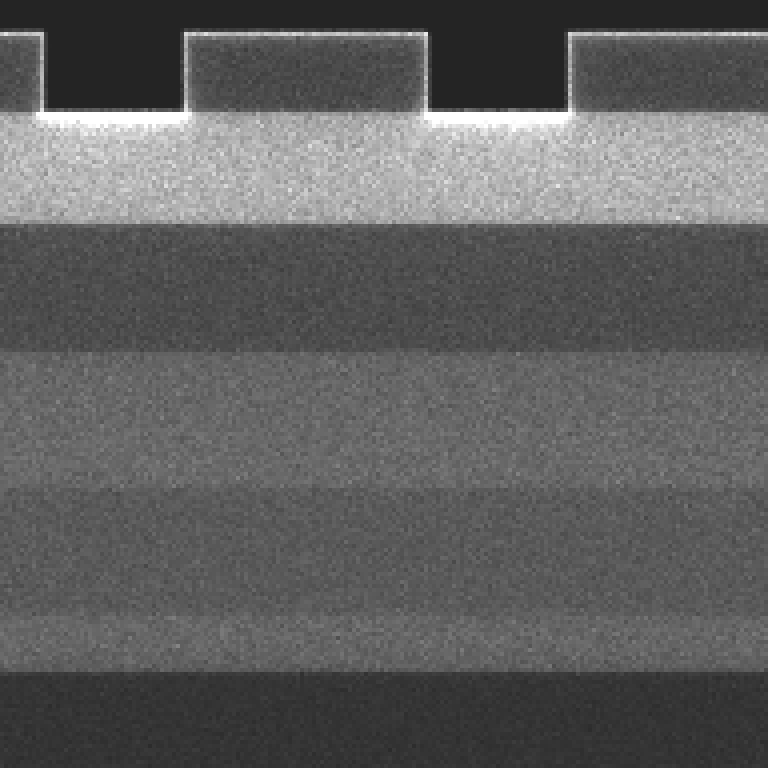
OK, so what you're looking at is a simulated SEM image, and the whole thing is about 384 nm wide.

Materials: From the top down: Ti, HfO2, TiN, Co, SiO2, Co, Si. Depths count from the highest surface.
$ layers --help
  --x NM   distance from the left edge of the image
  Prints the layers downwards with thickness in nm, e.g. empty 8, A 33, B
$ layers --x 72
empty 40, HfO2 56, TiN 64, Co 68, SiO2 64, Co 28, Si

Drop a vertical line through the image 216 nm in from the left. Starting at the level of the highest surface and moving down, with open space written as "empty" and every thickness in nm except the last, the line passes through empty 40, HfO2 56, TiN 64, Co 68, SiO2 64, Co 28, Si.